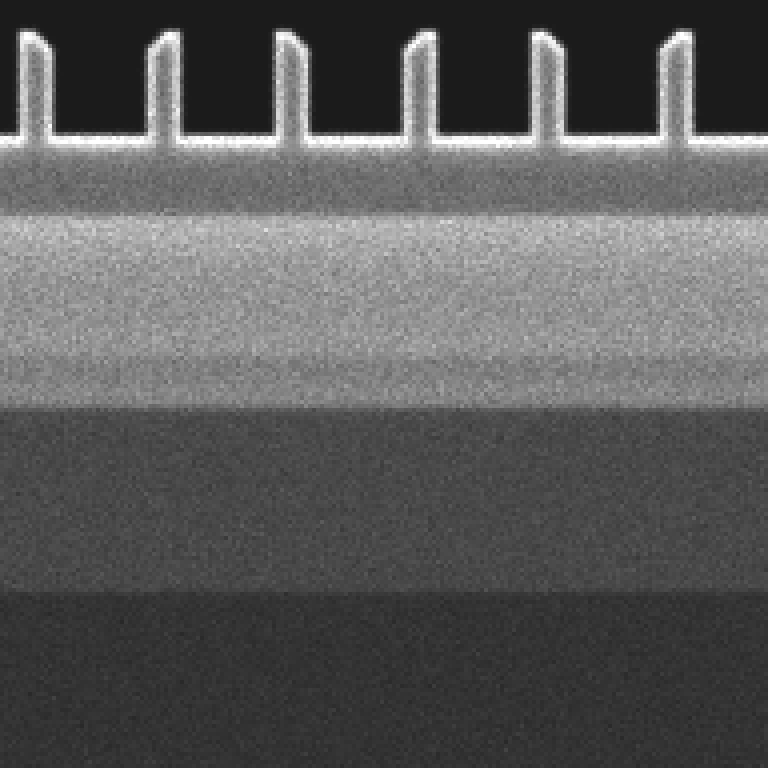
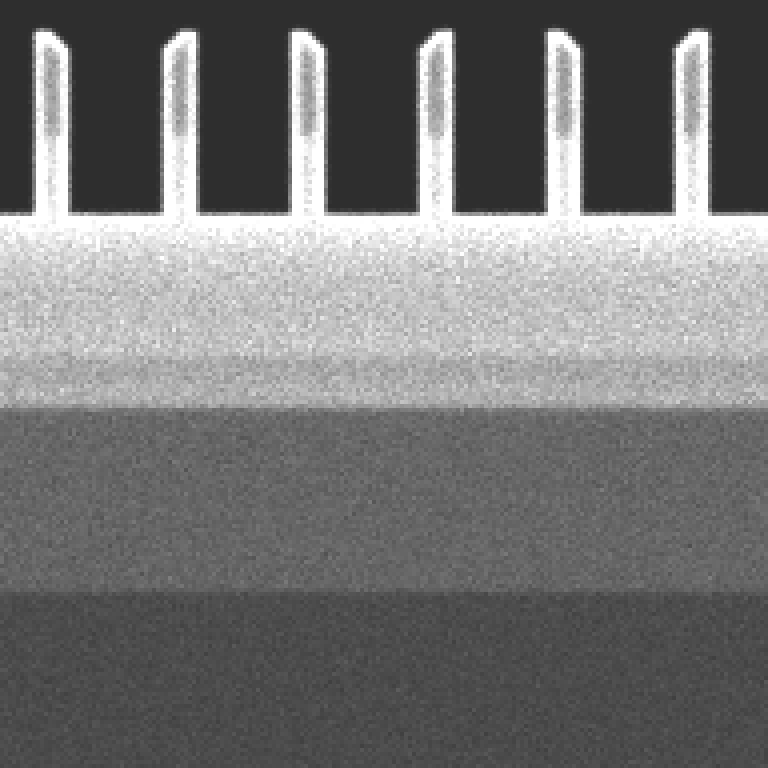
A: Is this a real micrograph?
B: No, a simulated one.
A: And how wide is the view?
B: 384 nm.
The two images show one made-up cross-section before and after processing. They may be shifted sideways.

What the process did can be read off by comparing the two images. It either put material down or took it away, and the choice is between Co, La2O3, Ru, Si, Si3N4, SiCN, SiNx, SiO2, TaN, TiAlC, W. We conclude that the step removed SiO2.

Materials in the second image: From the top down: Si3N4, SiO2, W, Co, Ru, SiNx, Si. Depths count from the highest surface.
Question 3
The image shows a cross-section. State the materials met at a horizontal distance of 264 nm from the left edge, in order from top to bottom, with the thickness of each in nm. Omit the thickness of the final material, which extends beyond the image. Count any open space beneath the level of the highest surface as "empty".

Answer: empty 92, W 70, Co 14, Ru 12, SiNx 92, Si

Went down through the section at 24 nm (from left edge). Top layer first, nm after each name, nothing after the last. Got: Si3N4 52, SiO2 40, W 70, Co 14, Ru 12, SiNx 92, Si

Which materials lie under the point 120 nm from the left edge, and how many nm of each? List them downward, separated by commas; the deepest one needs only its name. empty 92, W 70, Co 14, Ru 12, SiNx 92, Si